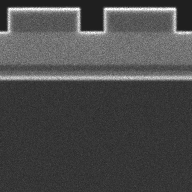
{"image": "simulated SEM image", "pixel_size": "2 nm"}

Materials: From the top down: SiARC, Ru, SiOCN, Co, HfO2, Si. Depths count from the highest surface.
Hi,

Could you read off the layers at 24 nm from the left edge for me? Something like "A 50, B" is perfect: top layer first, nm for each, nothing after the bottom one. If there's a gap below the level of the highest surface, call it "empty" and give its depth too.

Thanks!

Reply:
SiARC 48, Ru 66, SiOCN 12, Co 10, HfO2 8, Si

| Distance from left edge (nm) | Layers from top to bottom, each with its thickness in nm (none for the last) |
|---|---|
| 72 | SiARC 48, Ru 66, SiOCN 12, Co 10, HfO2 8, Si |